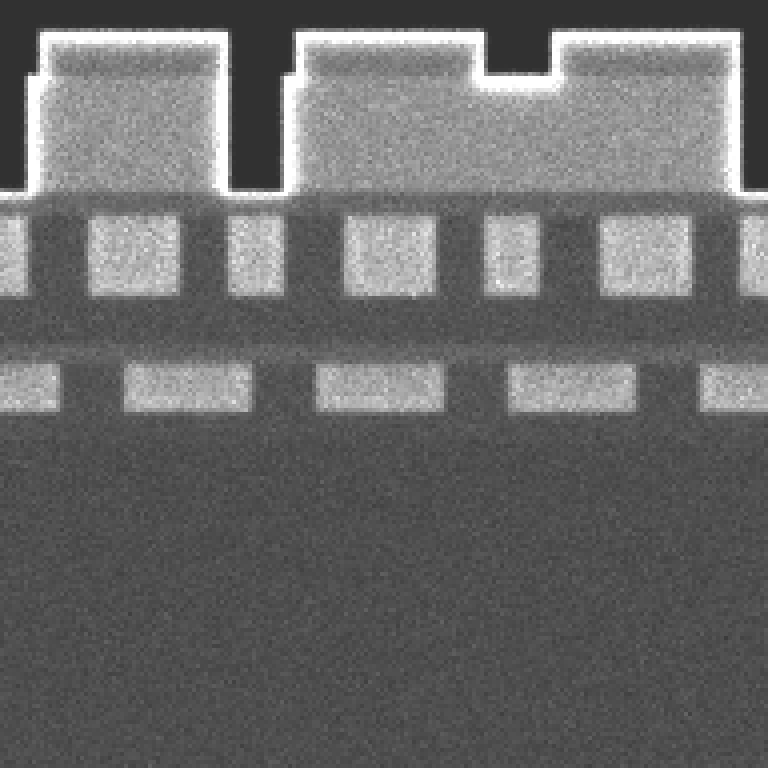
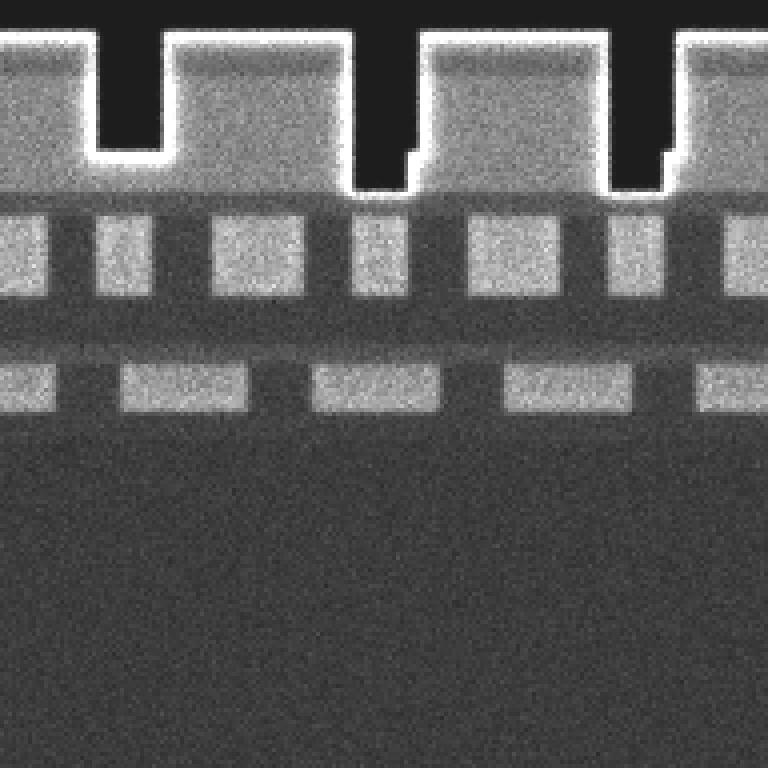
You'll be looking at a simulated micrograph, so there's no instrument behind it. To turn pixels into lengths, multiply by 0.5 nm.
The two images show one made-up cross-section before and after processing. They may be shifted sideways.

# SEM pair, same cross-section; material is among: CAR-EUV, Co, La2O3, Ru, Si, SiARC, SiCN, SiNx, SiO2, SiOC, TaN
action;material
removed;SiO2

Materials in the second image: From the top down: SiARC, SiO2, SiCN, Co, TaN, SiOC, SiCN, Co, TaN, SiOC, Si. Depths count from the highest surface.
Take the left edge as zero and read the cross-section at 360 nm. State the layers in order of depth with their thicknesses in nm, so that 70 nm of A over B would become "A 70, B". SiARC 22, SiO2 58, SiCN 12, SiOC 64, SiCN 10, Co 16, TaN 8, SiOC 14, Si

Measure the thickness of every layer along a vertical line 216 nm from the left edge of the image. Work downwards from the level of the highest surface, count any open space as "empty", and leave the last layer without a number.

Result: SiARC 22, SiO2 58, SiCN 12, SiOC 64, SiCN 10, TaN 24, SiOC 14, Si